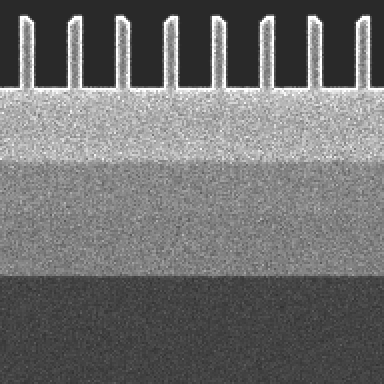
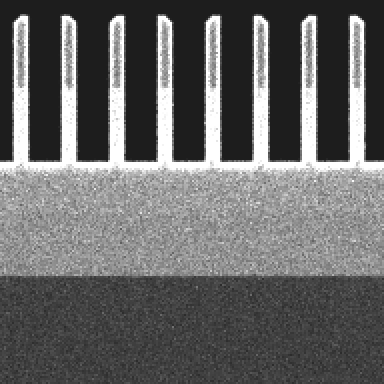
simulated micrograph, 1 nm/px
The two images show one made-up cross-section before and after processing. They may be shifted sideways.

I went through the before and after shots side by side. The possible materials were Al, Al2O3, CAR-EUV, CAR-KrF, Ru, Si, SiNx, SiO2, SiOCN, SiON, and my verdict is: removed, Ru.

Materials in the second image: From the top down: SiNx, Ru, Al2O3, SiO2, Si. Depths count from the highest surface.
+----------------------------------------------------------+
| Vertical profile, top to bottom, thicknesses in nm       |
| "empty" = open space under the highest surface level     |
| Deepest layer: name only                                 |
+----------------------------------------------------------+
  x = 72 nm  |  empty 4, SiNx 68, Ru 74, Al2O3 52, SiO2 62, Si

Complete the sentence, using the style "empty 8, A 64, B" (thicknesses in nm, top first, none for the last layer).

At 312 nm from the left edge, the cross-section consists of SiNx 72, Ru 74, Al2O3 52, SiO2 62, Si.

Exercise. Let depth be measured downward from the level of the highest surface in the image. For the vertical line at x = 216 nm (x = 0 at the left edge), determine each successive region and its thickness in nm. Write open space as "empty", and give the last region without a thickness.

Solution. SiNx 72, Ru 74, Al2O3 52, SiO2 62, Si